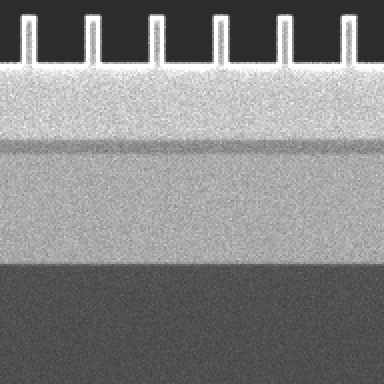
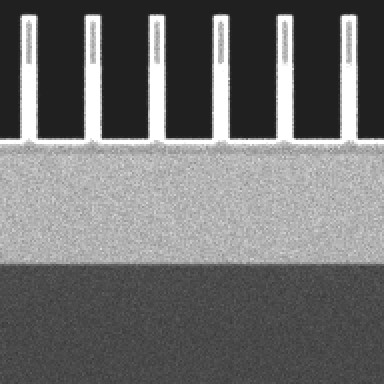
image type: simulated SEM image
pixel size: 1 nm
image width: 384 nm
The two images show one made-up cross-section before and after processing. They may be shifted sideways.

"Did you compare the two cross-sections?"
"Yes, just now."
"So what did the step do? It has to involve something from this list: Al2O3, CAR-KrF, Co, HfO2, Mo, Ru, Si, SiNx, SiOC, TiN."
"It removed Co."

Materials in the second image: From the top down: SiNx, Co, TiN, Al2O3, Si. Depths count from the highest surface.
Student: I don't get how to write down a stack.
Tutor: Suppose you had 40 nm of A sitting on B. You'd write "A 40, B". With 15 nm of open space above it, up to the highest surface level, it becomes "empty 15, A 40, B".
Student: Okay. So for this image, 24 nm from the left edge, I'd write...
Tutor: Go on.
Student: SiNx 48, Co 76, TiN 14, Al2O3 110, Si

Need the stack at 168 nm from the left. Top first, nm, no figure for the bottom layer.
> empty 124, TiN 14, Al2O3 110, Si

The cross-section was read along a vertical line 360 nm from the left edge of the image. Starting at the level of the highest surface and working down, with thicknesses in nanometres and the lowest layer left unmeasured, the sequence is empty 124, TiN 14, Al2O3 110, Si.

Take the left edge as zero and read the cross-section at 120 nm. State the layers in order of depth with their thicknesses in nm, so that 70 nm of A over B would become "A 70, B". empty 124, TiN 14, Al2O3 110, Si